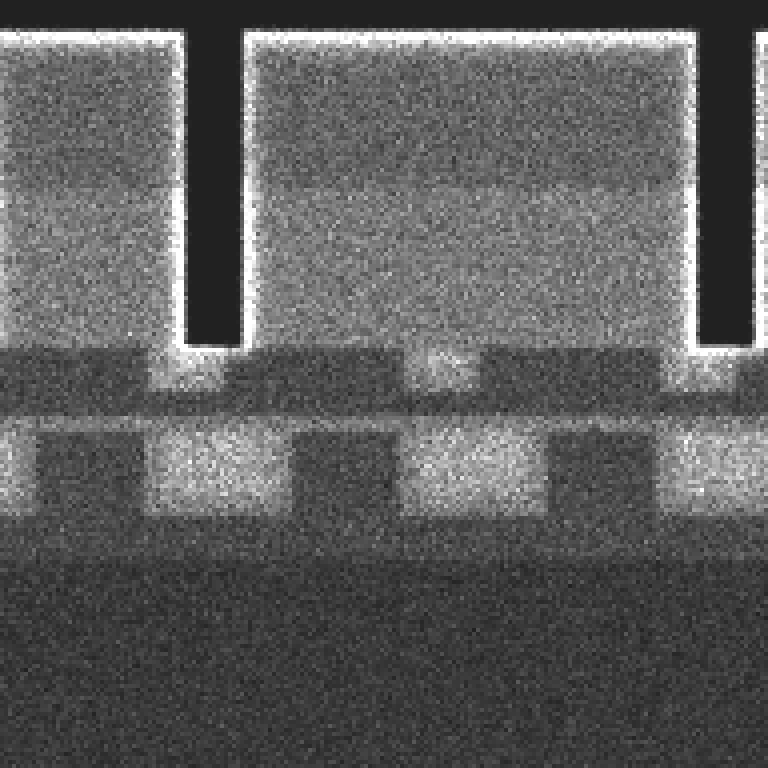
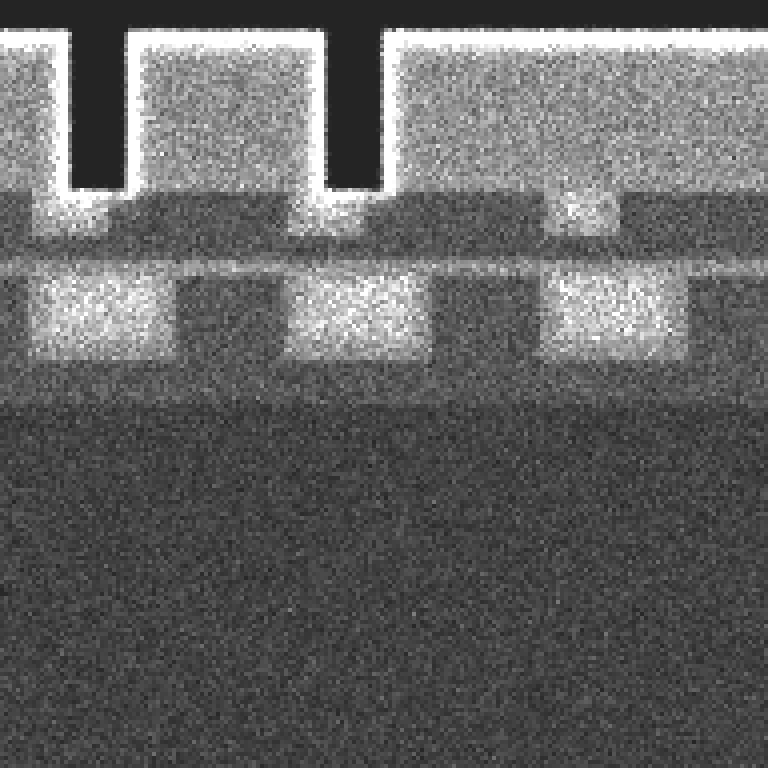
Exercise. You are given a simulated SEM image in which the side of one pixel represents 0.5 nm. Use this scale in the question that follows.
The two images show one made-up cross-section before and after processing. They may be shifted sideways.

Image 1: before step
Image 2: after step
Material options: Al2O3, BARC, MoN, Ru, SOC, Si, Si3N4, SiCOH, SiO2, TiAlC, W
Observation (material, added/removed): SOC, removed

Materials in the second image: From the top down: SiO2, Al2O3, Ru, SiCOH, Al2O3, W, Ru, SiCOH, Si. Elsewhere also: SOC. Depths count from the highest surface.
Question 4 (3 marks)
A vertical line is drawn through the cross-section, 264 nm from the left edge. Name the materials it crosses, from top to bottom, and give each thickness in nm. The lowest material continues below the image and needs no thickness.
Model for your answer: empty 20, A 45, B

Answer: SiO2 64, Al2O3 16, SiCOH 34, Al2O3 8, SiCOH 64, Si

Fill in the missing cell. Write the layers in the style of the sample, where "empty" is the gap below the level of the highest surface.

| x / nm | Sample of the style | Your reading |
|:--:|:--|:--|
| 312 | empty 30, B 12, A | SiO2 64, Al2O3 16, SiCOH 34, Al2O3 8, W 32, Ru 10, SiCOH 22, Si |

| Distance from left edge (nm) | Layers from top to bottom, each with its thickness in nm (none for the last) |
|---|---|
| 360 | SiO2 64, Al2O3 16, SiCOH 34, Al2O3 8, SiCOH 64, Si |